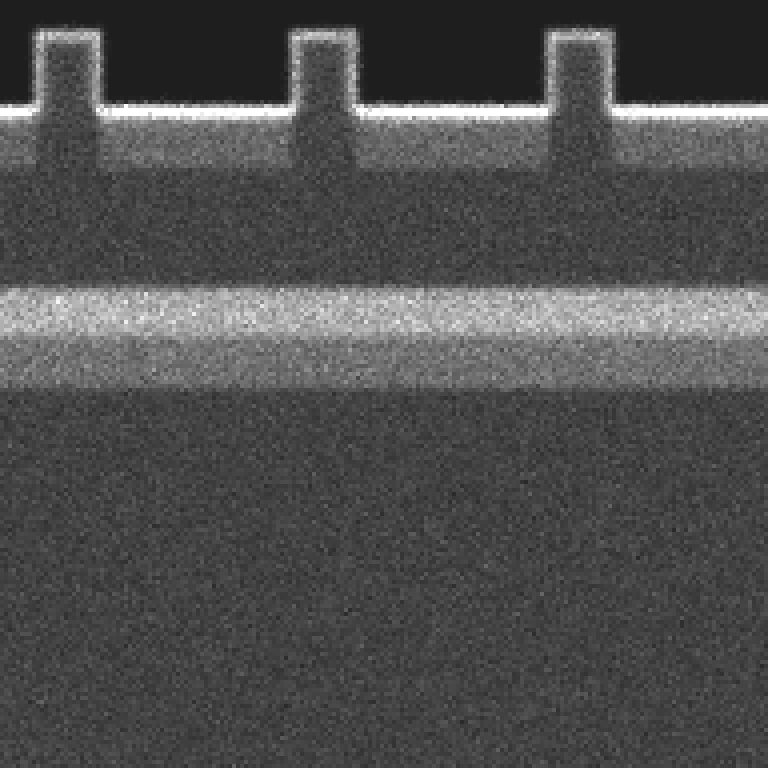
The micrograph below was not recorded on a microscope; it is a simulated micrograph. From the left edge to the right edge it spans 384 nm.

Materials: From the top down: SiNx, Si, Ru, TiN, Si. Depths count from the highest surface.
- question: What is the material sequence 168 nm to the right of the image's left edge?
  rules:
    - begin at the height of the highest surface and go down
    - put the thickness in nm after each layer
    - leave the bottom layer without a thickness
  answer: Si 128, Ru 24, TiN 26, Si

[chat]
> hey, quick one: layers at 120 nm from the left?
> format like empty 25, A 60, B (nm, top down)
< empty 38, SiNx 30, Si 60, Ru 24, TiN 26, Si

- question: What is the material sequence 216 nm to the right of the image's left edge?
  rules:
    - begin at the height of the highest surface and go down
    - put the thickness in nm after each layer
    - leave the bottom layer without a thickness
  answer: empty 38, SiNx 30, Si 60, Ru 24, TiN 26, Si